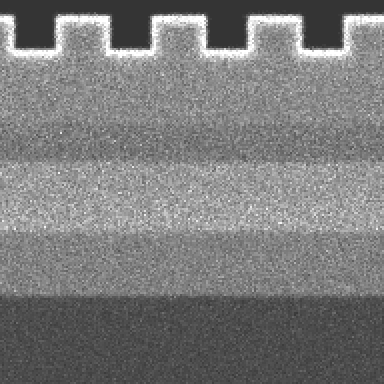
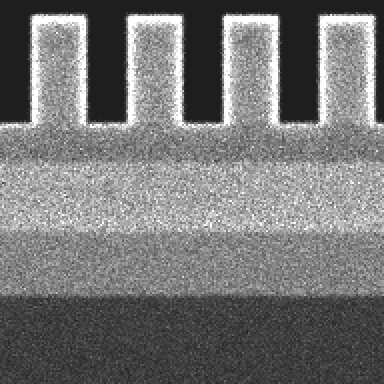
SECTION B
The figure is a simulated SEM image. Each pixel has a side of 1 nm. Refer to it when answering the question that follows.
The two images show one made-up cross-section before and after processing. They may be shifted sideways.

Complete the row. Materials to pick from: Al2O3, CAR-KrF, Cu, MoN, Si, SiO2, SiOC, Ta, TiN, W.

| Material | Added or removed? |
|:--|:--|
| Al2O3 | removed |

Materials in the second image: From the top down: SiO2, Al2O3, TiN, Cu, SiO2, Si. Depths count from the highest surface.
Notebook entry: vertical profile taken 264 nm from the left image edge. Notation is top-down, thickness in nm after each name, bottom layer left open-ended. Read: SiO2 34, Al2O3 74, TiN 38, Cu 70, SiO2 64, Si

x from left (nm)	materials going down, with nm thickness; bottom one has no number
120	empty 108, TiN 38, Cu 70, SiO2 64, Si